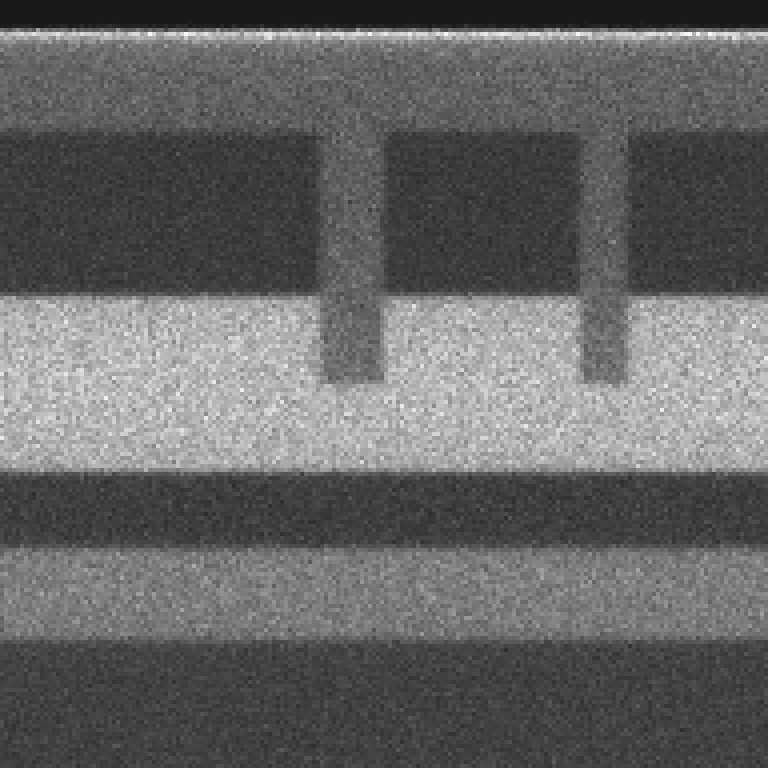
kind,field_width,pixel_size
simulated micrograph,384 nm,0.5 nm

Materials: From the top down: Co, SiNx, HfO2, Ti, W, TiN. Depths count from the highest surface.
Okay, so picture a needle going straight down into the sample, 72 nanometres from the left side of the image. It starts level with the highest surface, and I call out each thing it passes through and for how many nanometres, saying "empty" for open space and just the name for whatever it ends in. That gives Co 50, SiNx 82, HfO2 88, Ti 38, W 46, TiN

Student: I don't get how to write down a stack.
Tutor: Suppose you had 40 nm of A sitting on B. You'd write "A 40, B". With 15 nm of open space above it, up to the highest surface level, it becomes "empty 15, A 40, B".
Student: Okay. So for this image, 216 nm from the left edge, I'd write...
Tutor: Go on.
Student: Co 50, SiNx 82, HfO2 88, Ti 38, W 46, TiN